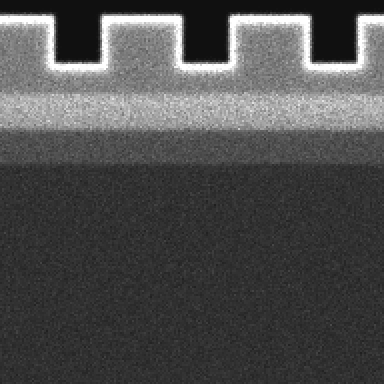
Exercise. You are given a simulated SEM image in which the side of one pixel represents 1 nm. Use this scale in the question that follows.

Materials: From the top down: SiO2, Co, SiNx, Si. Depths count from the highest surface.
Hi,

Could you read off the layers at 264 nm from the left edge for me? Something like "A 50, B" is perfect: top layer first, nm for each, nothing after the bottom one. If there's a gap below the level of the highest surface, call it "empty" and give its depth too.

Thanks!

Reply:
SiO2 78, Co 36, SiNx 34, Si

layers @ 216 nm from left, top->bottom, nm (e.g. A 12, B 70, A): empty 48, SiO2 30, Co 36, SiNx 34, Si